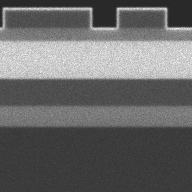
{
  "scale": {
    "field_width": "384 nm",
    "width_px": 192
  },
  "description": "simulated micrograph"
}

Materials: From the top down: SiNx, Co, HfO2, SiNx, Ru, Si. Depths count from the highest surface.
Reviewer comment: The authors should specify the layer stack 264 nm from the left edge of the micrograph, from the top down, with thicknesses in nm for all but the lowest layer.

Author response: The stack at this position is SiNx 40, Co 26, HfO2 76, SiNx 54, Ru 42, Si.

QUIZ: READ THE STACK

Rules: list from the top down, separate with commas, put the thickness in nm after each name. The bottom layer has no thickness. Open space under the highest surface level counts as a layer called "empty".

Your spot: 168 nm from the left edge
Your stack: SiNx 40, Co 26, HfO2 76, SiNx 54, Ru 42, Si